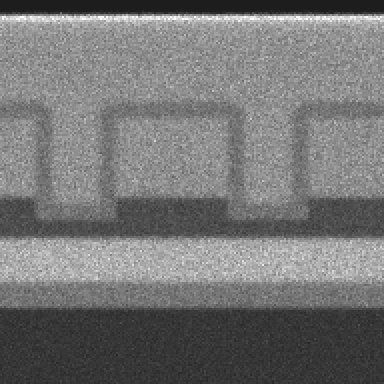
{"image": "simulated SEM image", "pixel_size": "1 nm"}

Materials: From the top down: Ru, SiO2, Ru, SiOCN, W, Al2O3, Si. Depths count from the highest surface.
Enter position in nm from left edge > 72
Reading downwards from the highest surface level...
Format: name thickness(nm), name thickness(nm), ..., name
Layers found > Ru 188, SiO2 16, SiOCN 18, W 44, Al2O3 26, Si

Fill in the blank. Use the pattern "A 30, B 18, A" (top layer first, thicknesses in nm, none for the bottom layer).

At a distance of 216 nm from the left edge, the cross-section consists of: Ru 86, SiO2 16, Ru 80, SiOCN 40, W 44, Al2O3 26, Si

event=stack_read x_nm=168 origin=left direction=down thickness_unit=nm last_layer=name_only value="Ru 86, SiO2 16, Ru 80, SiOCN 40, W 44, Al2O3 26, Si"